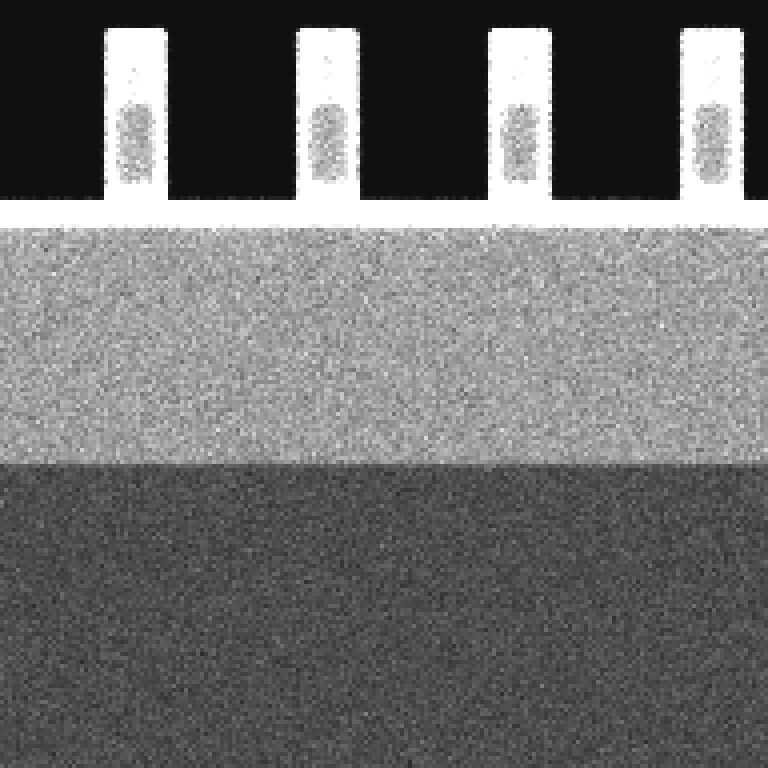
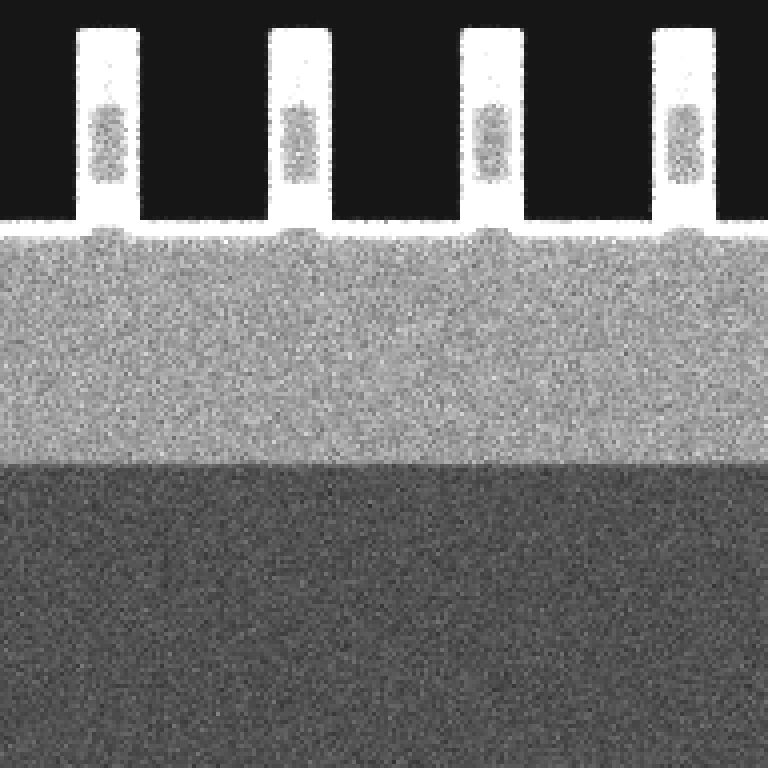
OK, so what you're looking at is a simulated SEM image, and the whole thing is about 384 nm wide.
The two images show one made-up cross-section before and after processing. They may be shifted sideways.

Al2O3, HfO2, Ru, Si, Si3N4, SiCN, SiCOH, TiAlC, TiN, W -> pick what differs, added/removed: HfO2 removed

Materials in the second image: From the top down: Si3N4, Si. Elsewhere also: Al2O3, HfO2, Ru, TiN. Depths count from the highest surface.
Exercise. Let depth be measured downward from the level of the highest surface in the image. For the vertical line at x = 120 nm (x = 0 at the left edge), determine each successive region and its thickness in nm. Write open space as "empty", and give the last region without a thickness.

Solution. empty 96, Si3N4 120, Si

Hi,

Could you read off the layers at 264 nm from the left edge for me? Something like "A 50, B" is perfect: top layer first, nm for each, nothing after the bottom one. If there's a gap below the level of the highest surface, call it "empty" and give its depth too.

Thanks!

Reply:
empty 96, Si3N4 120, Si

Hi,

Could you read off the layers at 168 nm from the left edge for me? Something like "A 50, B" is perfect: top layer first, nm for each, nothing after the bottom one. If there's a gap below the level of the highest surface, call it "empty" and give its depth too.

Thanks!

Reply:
empty 96, Si3N4 120, Si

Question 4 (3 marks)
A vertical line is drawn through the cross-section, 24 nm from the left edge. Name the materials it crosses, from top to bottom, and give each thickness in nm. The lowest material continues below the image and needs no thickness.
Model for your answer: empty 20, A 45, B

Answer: empty 96, Si3N4 120, Si